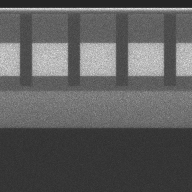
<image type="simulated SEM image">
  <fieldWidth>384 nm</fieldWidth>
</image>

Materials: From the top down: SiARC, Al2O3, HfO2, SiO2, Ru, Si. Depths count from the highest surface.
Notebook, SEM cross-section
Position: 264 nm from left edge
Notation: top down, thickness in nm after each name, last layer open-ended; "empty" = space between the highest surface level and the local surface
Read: SiARC 12, Al2O3 58, HfO2 66, SiO2 30, Ru 74, Si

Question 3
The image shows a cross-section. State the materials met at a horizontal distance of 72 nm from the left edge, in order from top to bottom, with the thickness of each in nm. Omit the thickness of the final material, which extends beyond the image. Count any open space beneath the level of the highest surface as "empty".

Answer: SiARC 12, Al2O3 58, HfO2 66, SiO2 30, Ru 74, Si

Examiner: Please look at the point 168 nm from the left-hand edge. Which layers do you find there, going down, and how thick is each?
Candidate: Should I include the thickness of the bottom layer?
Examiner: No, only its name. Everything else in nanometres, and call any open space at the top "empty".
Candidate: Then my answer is SiARC 12, Al2O3 58, HfO2 66, SiO2 30, Ru 74, Si